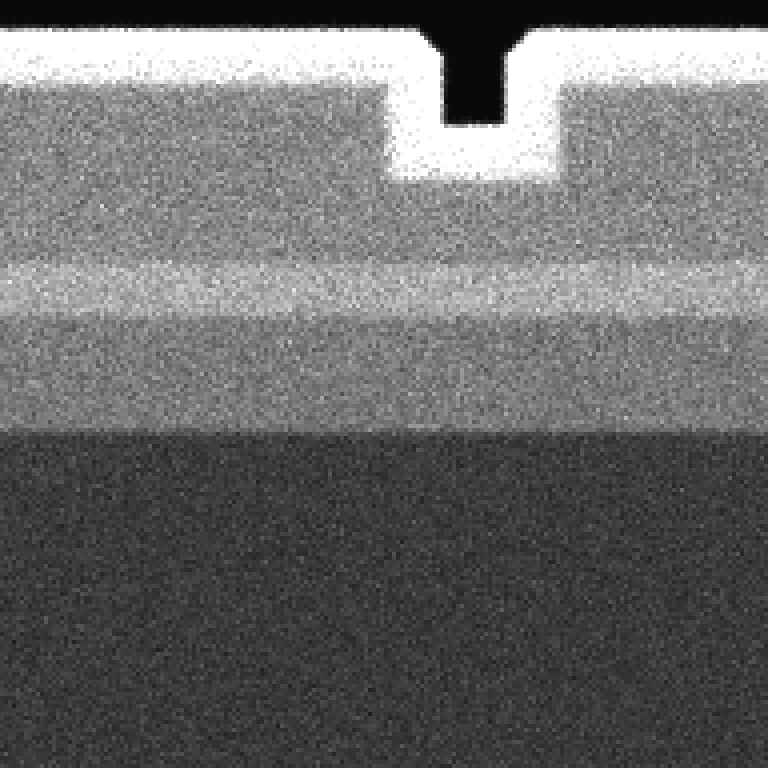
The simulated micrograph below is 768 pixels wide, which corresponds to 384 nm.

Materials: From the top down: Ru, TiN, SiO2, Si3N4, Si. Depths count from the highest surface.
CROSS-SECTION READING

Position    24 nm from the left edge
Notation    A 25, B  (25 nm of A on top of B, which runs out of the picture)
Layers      Ru 26, TiN 90, SiO2 26, Si3N4 58, Si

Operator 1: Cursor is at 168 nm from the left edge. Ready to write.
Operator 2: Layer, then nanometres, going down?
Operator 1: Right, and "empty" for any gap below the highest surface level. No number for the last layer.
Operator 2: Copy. Ru 26, TiN 90, SiO2 26, Si3N4 58, Si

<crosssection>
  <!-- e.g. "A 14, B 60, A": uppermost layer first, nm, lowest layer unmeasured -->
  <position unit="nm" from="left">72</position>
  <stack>Ru 26, TiN 90, SiO2 26, Si3N4 58, Si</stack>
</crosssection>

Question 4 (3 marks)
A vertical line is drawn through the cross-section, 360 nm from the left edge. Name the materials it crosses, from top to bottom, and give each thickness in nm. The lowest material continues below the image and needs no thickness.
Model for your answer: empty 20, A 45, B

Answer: Ru 26, TiN 90, SiO2 26, Si3N4 58, Si